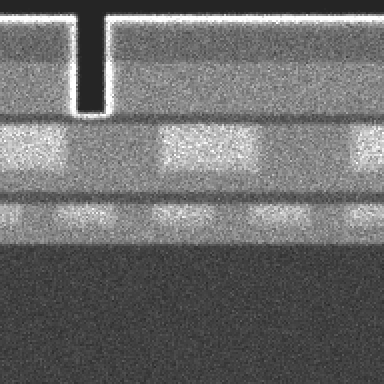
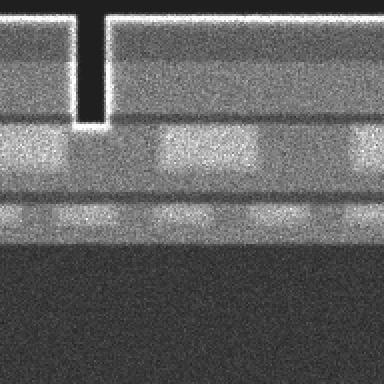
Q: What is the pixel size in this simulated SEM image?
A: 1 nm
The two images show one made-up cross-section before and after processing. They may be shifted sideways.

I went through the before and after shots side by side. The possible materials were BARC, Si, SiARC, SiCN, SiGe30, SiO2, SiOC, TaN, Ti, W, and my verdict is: removed, SiCN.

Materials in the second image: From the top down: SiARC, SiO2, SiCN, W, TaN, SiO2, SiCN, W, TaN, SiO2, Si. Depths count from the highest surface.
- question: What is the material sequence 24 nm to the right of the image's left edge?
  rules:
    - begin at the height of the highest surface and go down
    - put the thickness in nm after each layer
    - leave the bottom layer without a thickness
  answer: SiARC 46, SiO2 52, SiCN 10, W 40, TaN 8, SiO2 20, SiCN 12, SiO2 40, Si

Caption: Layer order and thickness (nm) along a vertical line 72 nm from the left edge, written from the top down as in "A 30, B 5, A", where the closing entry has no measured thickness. SiARC 46, SiO2 52, SiCN 10, SiO2 68, SiCN 12, W 14, TaN 8, SiO2 18, Si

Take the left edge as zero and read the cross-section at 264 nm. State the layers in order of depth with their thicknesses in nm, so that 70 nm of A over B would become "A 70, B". SiARC 46, SiO2 52, SiCN 10, SiO2 68, SiCN 12, W 14, TaN 8, SiO2 18, Si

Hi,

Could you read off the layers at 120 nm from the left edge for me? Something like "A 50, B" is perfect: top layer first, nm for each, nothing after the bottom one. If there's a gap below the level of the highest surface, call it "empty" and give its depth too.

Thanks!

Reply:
SiARC 46, SiO2 52, SiCN 10, SiO2 68, SiCN 12, SiO2 40, Si